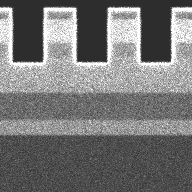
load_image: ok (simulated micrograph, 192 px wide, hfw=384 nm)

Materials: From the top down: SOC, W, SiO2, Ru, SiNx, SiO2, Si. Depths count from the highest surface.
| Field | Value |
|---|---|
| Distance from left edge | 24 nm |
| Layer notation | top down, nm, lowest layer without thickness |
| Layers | empty 110, Ru 60, SiNx 54, SiO2 30, Si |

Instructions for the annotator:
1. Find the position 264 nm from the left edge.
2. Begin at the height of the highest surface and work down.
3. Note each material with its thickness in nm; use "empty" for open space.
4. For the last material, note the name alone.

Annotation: SOC 22, W 48, SiO2 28, Ru 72, SiNx 54, SiO2 30, Si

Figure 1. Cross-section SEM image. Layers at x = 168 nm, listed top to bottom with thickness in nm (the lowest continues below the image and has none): empty 110, Ru 60, SiNx 54, SiO2 30, Si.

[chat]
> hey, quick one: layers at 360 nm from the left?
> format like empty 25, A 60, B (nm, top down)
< SOC 22, W 48, SiO2 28, Ru 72, SiNx 54, SiO2 30, Si